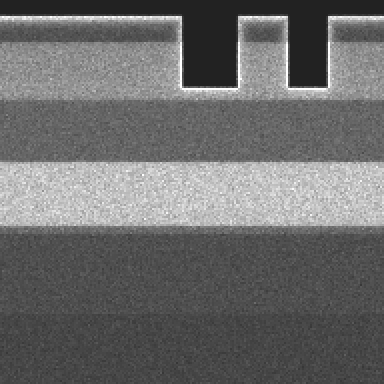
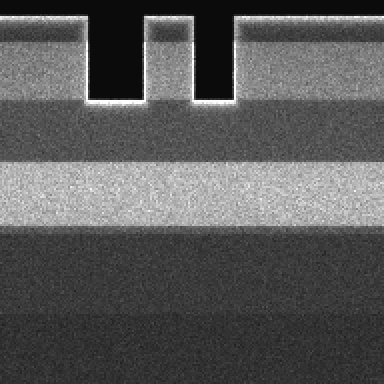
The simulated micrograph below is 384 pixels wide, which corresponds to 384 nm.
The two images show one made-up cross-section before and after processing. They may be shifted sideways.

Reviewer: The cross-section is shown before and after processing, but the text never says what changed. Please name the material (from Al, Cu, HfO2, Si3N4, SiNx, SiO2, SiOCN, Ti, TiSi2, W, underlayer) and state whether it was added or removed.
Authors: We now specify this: W, removed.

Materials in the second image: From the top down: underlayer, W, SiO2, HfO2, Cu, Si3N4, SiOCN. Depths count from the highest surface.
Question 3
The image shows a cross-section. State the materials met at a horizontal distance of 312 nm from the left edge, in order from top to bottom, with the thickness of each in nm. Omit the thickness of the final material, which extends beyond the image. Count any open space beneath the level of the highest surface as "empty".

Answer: underlayer 26, W 58, SiO2 62, HfO2 64, Cu 8, Si3N4 80, SiOCN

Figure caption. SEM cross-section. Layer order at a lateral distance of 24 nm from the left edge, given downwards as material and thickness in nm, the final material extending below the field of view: underlayer 26, W 58, SiO2 62, HfO2 64, Cu 8, Si3N4 80, SiOCN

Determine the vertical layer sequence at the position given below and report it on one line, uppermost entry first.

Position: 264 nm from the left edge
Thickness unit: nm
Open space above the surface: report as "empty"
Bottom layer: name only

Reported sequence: underlayer 26, W 58, SiO2 62, HfO2 64, Cu 8, Si3N4 80, SiOCN